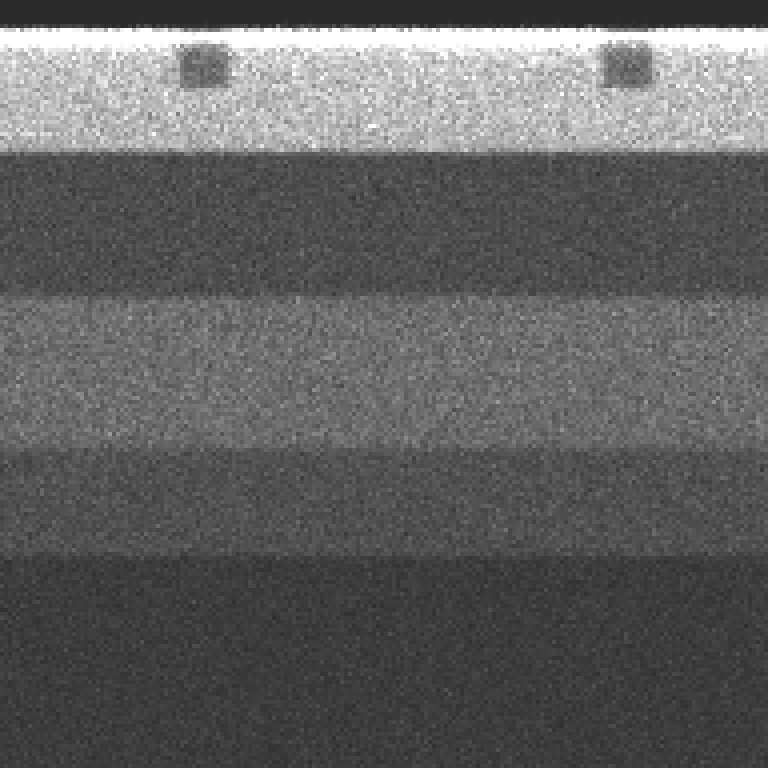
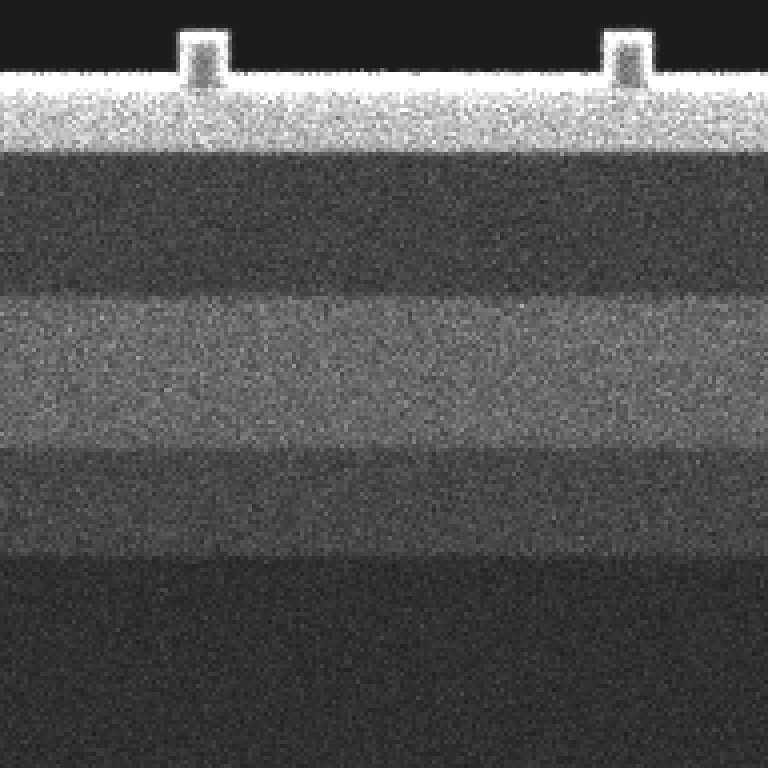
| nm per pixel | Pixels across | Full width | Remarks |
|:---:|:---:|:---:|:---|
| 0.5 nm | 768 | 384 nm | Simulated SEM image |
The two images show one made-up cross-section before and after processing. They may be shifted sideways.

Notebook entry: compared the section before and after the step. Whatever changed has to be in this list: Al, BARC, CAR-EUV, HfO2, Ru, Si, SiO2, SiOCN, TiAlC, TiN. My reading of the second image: HfO2 removed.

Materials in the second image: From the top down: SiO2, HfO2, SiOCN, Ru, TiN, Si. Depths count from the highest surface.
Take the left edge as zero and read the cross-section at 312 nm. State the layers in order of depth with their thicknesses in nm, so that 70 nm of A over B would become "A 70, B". SiO2 28, HfO2 32, SiOCN 72, Ru 76, TiN 54, Si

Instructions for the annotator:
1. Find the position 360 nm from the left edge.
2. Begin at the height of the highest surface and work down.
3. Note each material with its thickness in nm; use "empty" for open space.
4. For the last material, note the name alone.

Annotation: empty 22, HfO2 38, SiOCN 72, Ru 76, TiN 54, Si